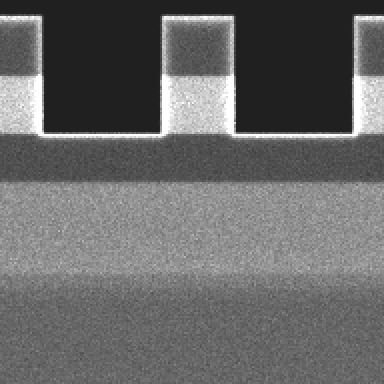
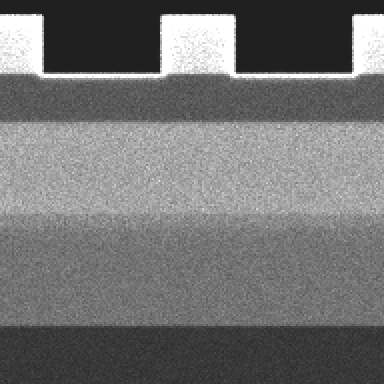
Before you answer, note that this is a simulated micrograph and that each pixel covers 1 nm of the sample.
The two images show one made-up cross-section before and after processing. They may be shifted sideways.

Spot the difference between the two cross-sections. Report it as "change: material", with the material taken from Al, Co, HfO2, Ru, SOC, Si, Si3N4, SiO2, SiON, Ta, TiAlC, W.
removed: SOC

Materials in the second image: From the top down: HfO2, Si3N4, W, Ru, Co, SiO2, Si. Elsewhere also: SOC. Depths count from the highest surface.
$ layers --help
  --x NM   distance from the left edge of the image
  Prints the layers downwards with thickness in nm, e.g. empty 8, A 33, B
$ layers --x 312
empty 58, Si3N4 48, W 92, Ru 14, Co 12, SiO2 86, Si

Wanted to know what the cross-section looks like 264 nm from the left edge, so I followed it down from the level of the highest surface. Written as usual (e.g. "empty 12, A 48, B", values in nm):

empty 58, Si3N4 48, W 92, Ru 14, Co 12, SiO2 86, Si